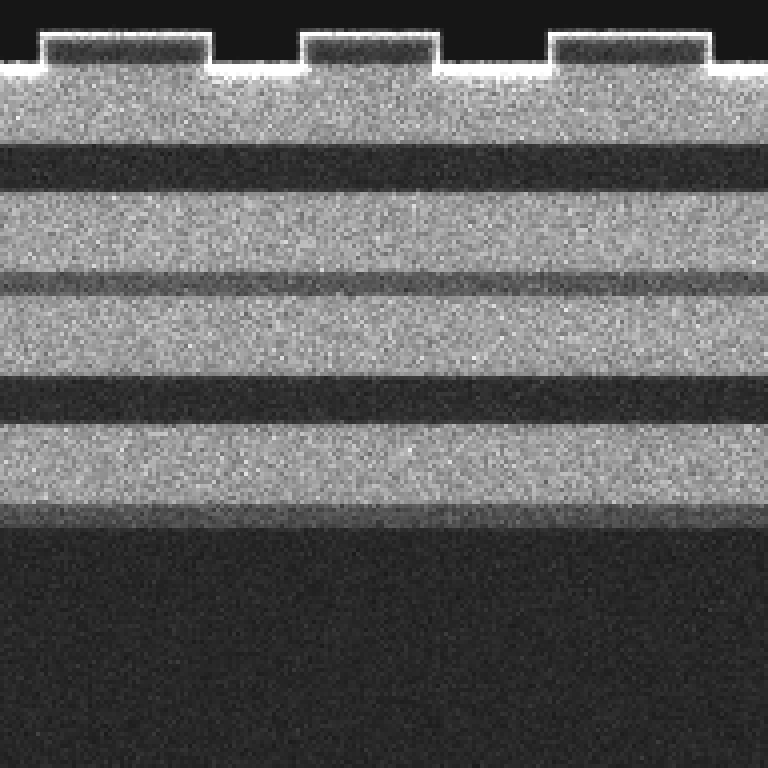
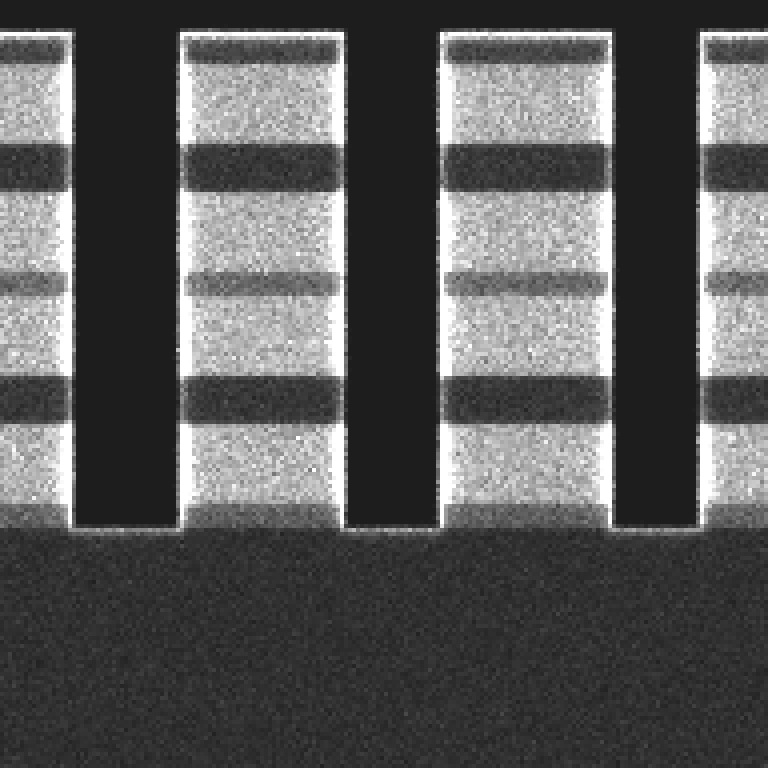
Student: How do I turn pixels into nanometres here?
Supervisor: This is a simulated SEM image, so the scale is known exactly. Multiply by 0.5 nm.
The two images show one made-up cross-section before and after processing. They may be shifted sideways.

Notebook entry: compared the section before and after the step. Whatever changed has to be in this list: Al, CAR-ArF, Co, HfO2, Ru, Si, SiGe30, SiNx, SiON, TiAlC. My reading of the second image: Co and HfO2 and SiGe30 removed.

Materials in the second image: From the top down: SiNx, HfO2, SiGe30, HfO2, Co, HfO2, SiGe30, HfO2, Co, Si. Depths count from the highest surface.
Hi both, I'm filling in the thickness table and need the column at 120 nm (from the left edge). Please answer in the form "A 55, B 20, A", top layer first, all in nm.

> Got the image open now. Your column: SiNx 16, HfO2 40, SiGe30 24, HfO2 40, Co 12, HfO2 40, SiGe30 24, HfO2 40, Co 12, Si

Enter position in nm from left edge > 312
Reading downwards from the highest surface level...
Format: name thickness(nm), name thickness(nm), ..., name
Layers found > empty 248, Si